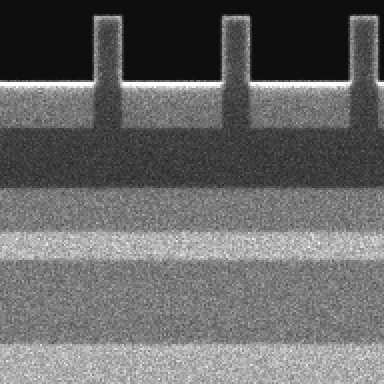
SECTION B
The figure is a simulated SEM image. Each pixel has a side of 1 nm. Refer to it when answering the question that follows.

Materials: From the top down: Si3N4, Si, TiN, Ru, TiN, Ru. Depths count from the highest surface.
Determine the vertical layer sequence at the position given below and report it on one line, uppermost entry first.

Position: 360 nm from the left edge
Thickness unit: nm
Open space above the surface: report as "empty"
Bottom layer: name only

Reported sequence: Si 172, TiN 44, Ru 28, TiN 84, Ru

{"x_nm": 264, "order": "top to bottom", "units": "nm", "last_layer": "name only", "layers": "empty 66, Si3N4 46, Si 60, TiN 44, Ru 28, TiN 84, Ru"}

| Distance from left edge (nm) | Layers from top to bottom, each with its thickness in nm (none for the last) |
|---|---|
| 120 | Si 172, TiN 44, Ru 28, TiN 84, Ru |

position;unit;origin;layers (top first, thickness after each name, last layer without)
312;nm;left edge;empty 66, Si3N4 46, Si 60, TiN 44, Ru 28, TiN 84, Ru